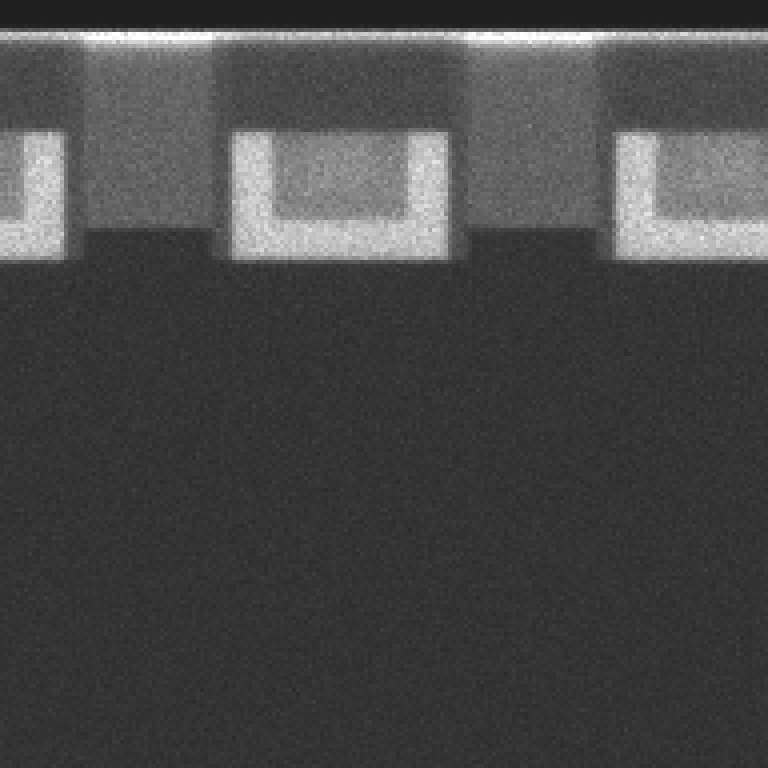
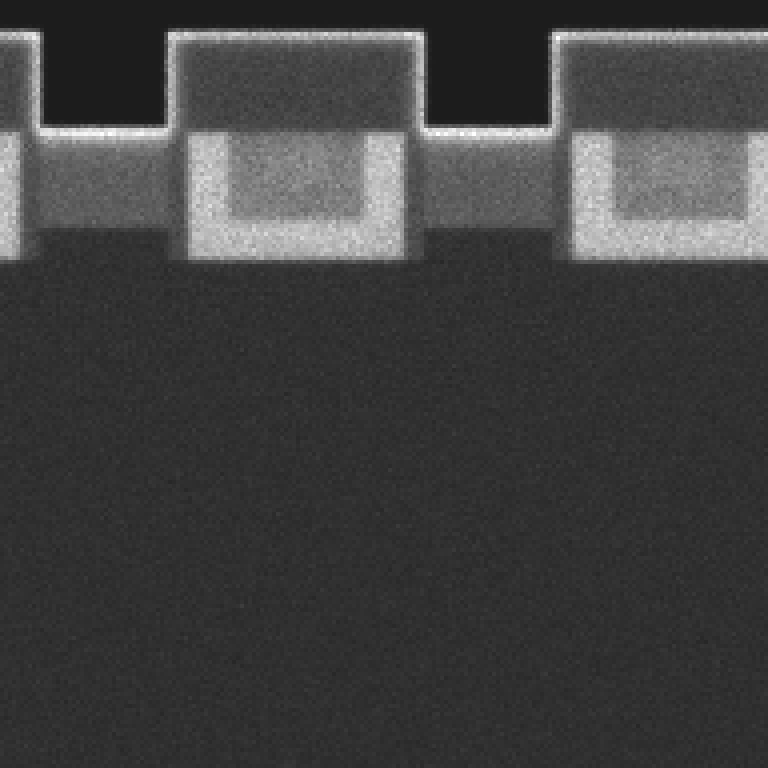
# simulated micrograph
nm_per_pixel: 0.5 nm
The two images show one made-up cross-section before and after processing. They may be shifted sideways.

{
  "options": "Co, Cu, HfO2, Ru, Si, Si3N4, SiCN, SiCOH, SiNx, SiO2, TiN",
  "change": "removed",
  "material": "SiO2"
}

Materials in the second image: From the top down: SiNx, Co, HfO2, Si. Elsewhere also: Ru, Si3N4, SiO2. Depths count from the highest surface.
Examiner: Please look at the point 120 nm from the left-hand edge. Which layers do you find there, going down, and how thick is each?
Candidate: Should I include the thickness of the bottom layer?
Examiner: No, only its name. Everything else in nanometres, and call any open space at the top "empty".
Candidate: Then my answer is SiNx 50, Co 44, HfO2 20, Si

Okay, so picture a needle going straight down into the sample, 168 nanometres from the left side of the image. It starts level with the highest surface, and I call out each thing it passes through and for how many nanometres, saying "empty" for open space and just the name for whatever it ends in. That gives SiNx 50, Co 44, HfO2 20, Si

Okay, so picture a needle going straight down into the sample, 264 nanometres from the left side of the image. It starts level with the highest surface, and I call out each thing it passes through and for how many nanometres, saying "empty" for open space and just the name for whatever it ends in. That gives empty 48, SiO2 50, Si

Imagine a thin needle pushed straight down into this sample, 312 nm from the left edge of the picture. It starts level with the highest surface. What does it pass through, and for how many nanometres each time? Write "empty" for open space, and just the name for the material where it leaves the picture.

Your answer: SiNx 50, Co 44, HfO2 20, Si